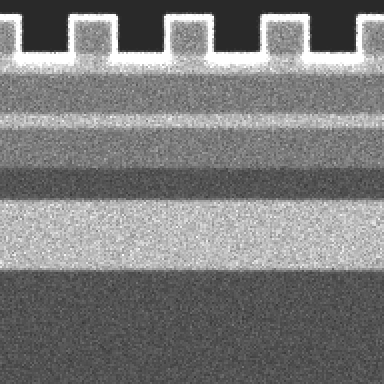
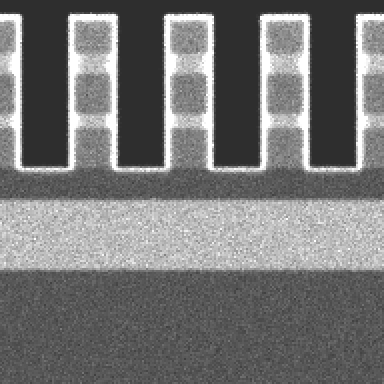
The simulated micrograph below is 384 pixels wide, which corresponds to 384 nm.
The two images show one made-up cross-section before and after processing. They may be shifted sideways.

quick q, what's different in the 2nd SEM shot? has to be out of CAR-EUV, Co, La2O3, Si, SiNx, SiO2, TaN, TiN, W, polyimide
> SiNx and SiO2 removed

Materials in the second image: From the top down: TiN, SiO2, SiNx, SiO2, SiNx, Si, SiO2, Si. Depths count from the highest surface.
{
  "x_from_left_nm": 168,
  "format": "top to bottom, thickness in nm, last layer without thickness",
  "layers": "TiN 38, SiO2 20, SiNx 40, SiO2 14, SiNx 40, Si 32, SiO2 70, Si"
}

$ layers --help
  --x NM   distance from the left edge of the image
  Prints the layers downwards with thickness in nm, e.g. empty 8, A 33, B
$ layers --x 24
empty 152, Si 32, SiO2 70, Si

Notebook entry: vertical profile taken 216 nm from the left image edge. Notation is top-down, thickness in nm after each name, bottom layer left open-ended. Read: empty 152, Si 32, SiO2 70, Si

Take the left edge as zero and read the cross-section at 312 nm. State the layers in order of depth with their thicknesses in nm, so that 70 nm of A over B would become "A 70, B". empty 152, Si 32, SiO2 70, Si